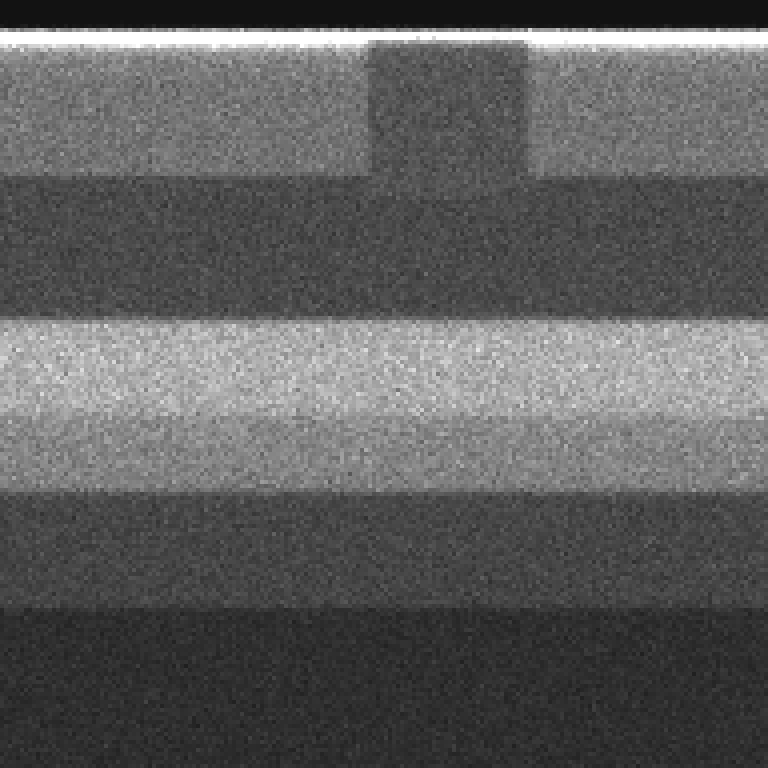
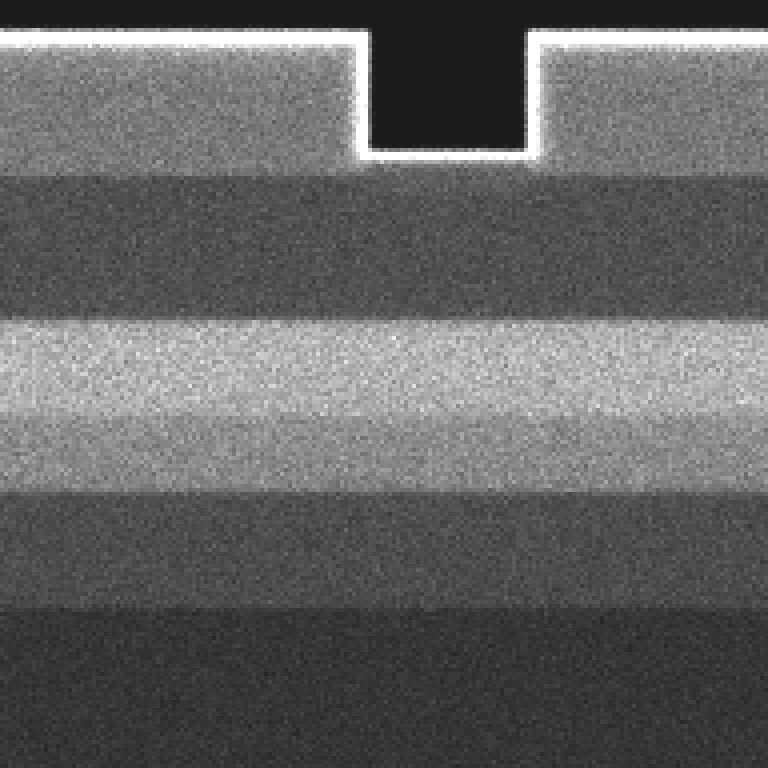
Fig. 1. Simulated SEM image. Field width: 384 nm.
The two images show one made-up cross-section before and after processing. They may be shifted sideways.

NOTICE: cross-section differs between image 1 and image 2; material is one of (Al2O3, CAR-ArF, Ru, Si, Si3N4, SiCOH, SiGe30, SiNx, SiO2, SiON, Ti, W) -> removed: Si3N4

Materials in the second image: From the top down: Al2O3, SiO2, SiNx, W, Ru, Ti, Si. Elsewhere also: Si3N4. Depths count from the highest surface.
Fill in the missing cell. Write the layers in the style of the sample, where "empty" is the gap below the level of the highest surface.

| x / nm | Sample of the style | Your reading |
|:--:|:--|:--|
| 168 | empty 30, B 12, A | Al2O3 24, SiO2 48, SiNx 72, W 48, Ru 38, Ti 58, Si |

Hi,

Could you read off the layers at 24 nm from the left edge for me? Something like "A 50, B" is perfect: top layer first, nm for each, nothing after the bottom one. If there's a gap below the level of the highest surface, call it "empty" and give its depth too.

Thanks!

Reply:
Al2O3 24, SiO2 48, SiNx 72, W 48, Ru 38, Ti 58, Si